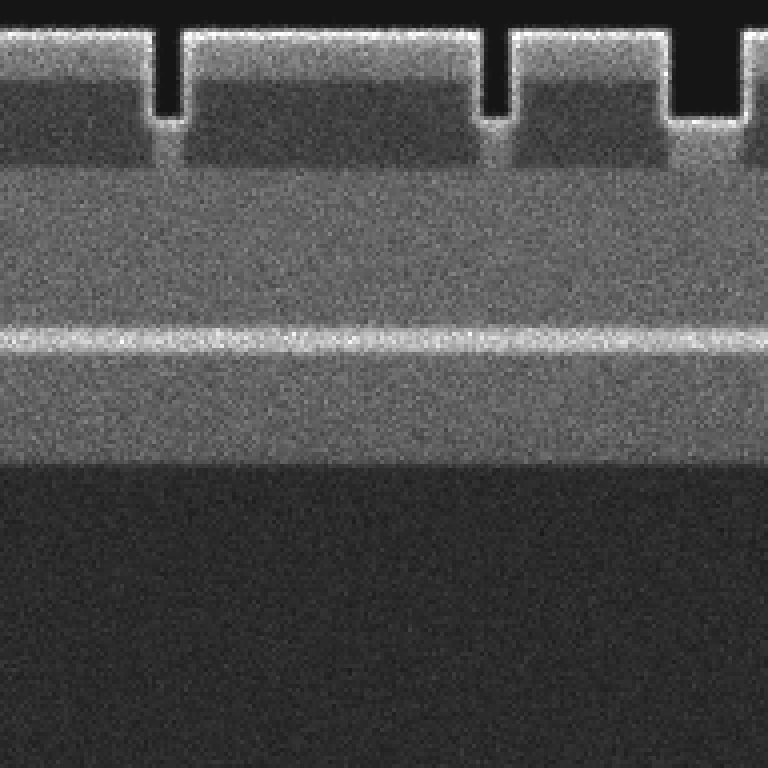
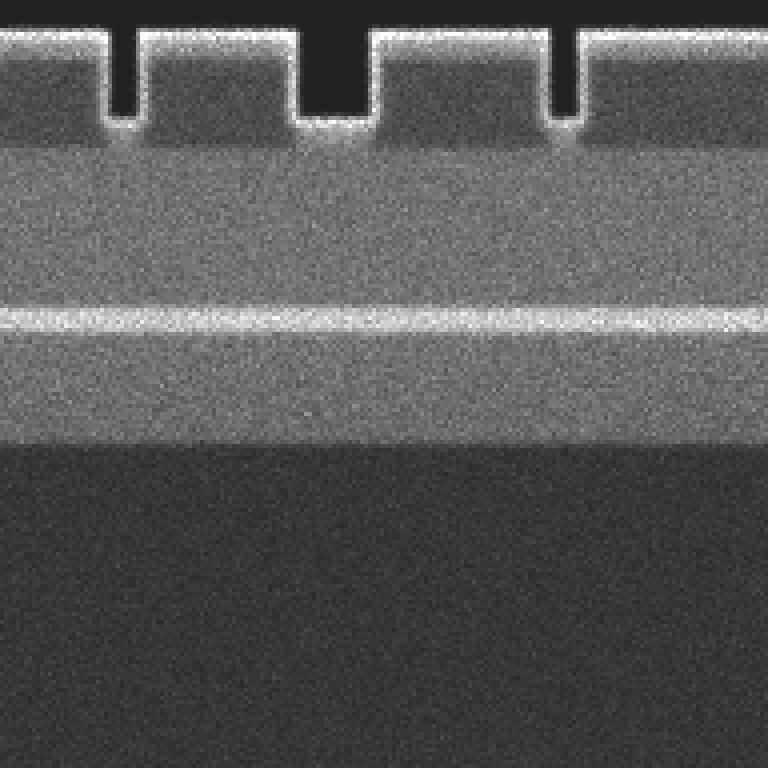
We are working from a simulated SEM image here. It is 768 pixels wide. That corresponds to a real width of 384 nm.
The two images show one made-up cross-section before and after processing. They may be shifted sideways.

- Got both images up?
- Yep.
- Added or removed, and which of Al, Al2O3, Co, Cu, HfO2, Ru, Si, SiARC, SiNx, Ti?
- removed, Ru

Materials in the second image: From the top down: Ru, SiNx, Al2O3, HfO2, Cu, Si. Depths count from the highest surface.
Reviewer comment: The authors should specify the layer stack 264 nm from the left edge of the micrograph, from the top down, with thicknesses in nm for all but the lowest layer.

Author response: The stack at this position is Ru 14, SiNx 44, Al2O3 80, HfO2 12, Cu 56, Si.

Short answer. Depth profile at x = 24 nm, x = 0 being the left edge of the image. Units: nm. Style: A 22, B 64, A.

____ Ru 14, SiNx 44, Al2O3 80, HfO2 12, Cu 56, Si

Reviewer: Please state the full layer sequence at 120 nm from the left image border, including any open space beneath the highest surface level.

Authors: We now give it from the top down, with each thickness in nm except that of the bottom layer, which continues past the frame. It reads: Ru 14, SiNx 44, Al2O3 80, HfO2 12, Cu 56, Si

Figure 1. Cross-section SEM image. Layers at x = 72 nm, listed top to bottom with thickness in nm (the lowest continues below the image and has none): Ru 14, SiNx 44, Al2O3 80, HfO2 12, Cu 56, Si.